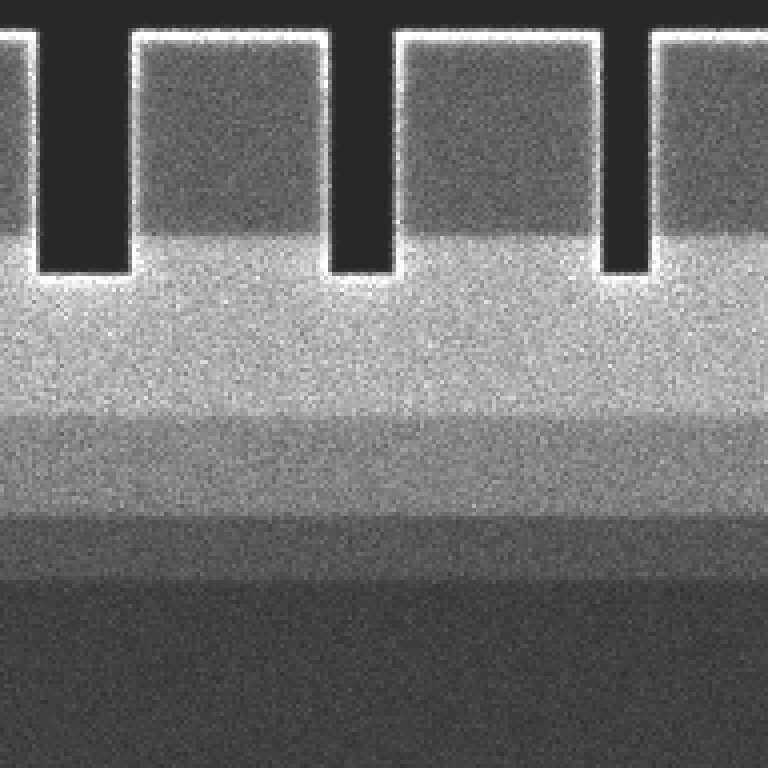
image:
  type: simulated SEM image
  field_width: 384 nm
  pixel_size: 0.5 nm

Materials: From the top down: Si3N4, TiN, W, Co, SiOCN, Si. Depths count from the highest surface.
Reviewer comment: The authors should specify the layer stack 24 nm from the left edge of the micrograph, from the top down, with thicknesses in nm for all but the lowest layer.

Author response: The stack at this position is empty 122, W 70, Co 50, SiOCN 32, Si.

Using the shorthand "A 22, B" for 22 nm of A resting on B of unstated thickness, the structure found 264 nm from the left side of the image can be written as Si3N4 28, TiN 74, W 90, Co 50, SiOCN 32, Si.